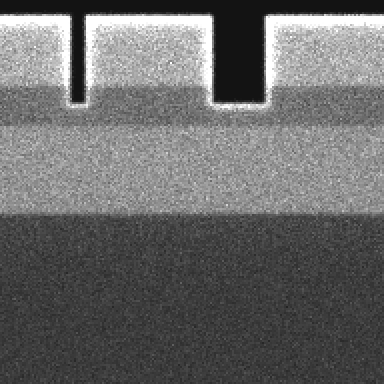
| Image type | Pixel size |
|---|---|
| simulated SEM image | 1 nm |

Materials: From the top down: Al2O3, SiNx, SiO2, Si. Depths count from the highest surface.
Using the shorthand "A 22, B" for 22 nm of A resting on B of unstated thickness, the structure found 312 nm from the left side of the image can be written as Al2O3 70, SiNx 40, SiO2 88, Si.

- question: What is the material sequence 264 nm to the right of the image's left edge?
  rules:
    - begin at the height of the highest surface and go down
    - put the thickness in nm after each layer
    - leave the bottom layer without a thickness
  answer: empty 88, SiNx 22, SiO2 88, Si